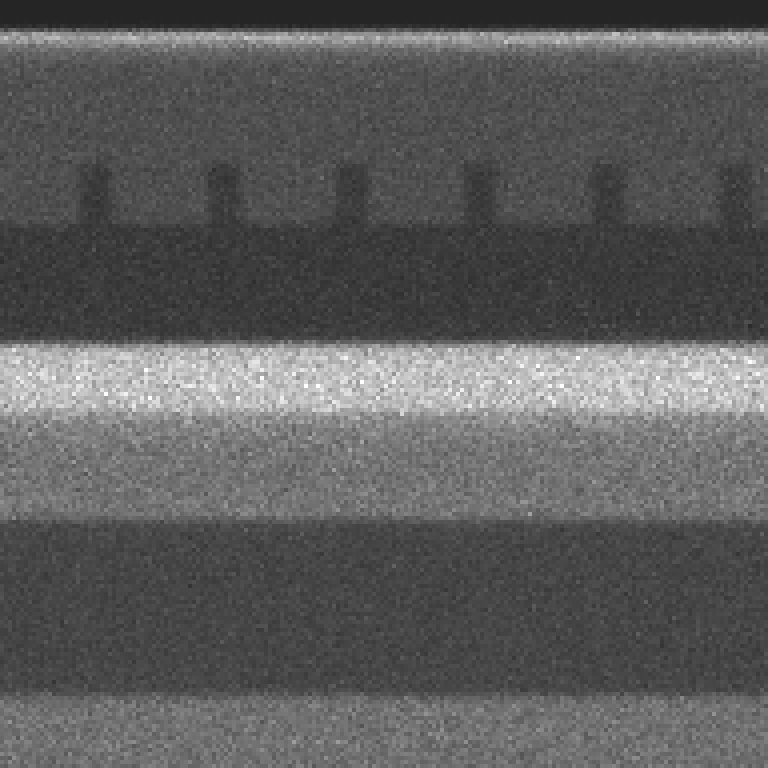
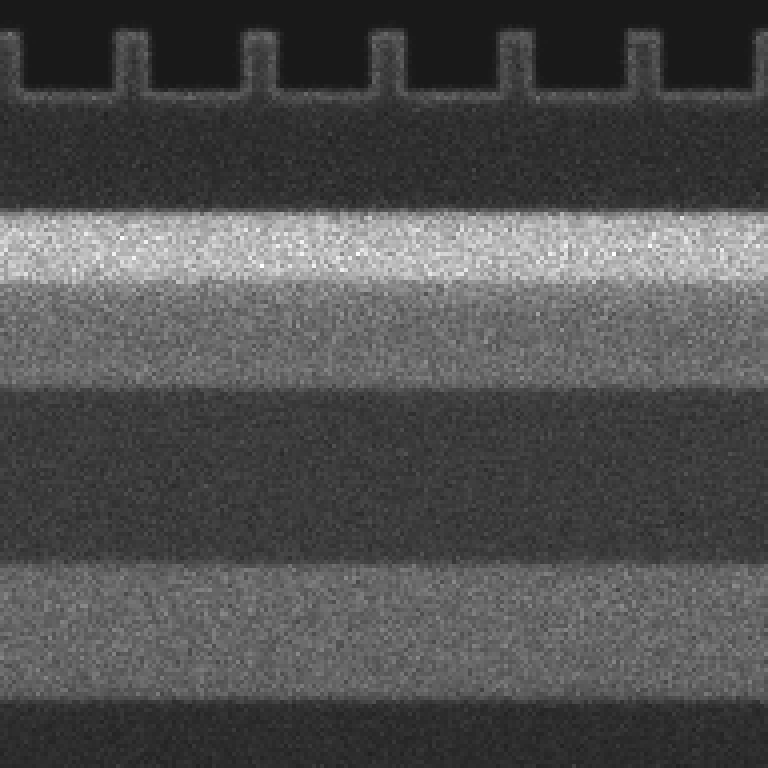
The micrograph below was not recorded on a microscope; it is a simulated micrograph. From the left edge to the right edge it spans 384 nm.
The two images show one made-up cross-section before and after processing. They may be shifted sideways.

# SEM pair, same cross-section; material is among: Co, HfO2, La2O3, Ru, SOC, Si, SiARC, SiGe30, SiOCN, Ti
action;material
removed;SOC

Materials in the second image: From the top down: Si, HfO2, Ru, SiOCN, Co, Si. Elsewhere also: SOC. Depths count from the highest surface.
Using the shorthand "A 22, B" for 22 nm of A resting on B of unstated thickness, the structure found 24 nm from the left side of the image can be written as empty 30, Si 60, HfO2 34, Ru 54, SiOCN 88, Co 68, Si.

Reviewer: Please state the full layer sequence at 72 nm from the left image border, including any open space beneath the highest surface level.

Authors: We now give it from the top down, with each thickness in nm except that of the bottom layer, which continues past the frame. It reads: Si 90, HfO2 34, Ru 54, SiOCN 88, Co 68, Si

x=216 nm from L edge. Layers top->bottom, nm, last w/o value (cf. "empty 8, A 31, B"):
empty 30, Si 60, HfO2 34, Ru 54, SiOCN 88, Co 68, Si